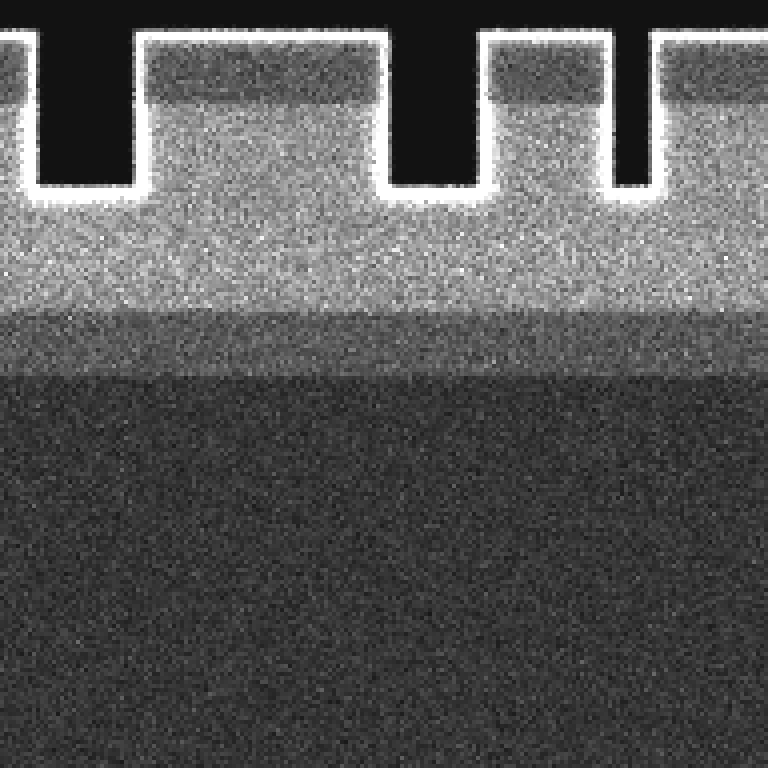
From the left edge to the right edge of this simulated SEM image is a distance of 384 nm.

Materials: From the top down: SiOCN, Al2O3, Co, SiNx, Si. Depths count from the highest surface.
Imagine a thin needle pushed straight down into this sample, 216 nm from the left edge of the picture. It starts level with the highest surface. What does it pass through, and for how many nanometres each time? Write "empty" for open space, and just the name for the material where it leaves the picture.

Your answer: empty 78, Al2O3 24, Co 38, SiNx 32, Si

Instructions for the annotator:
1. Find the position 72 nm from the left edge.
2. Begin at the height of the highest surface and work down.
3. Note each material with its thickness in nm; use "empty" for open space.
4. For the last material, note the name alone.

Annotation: SiOCN 36, Al2O3 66, Co 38, SiNx 32, Si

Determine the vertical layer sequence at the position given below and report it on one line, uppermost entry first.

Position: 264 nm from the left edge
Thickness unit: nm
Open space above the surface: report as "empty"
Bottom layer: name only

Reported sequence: SiOCN 36, Al2O3 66, Co 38, SiNx 32, Si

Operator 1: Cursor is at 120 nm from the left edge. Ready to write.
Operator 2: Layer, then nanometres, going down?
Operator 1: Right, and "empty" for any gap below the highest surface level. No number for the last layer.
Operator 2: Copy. SiOCN 36, Al2O3 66, Co 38, SiNx 32, Si